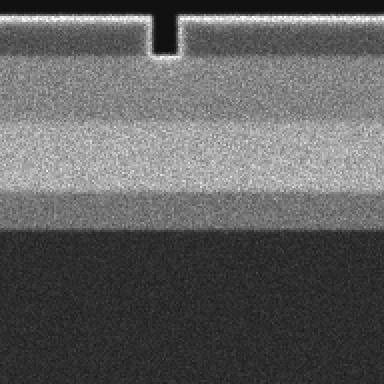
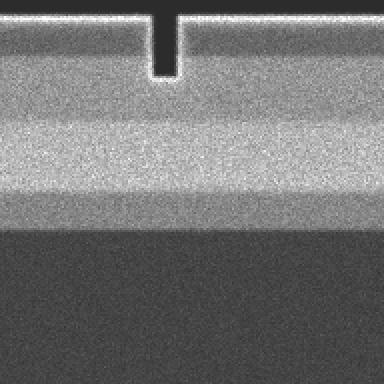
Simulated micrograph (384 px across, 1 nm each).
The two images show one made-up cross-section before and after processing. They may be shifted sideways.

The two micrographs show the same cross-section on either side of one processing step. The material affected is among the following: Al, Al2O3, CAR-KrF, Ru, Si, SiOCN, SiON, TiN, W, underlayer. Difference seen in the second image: Ru removed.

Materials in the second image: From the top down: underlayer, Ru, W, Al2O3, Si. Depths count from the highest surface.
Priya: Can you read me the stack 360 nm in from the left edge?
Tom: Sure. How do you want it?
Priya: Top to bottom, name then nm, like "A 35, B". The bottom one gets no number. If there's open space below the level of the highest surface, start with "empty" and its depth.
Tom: underlayer 40, Ru 66, W 70, Al2O3 38, Si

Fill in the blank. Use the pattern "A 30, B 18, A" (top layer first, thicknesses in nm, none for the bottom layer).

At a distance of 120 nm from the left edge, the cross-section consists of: underlayer 40, Ru 66, W 70, Al2O3 38, Si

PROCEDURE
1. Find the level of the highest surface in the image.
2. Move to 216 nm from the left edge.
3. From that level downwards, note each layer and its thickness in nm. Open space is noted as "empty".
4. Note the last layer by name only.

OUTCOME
underlayer 40, Ru 66, W 70, Al2O3 38, Si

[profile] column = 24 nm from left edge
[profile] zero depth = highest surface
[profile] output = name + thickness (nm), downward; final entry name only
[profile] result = underlayer 40, Ru 66, W 70, Al2O3 38, Si